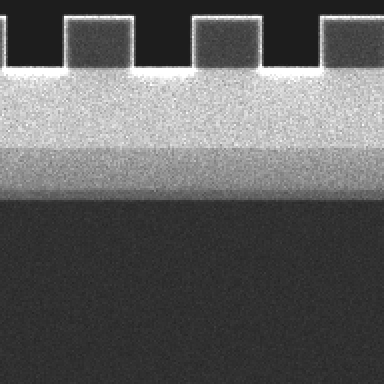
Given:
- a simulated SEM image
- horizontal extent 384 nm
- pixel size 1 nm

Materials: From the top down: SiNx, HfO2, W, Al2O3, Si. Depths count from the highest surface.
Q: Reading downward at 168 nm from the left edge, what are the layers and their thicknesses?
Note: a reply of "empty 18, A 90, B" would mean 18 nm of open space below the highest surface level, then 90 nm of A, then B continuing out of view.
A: empty 52, HfO2 80, W 42, Al2O3 10, Si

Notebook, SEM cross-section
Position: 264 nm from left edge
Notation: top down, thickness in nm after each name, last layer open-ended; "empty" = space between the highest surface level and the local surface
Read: empty 52, HfO2 80, W 42, Al2O3 10, Si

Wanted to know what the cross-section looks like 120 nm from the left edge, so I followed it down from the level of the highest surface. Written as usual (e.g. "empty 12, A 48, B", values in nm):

SiNx 52, HfO2 80, W 42, Al2O3 10, Si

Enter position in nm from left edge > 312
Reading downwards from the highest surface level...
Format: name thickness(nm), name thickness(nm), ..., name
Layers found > empty 52, HfO2 80, W 42, Al2O3 10, Si